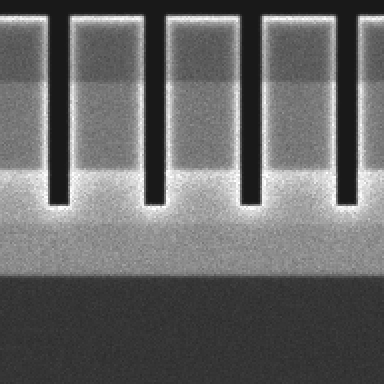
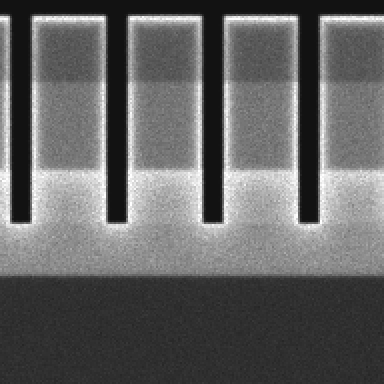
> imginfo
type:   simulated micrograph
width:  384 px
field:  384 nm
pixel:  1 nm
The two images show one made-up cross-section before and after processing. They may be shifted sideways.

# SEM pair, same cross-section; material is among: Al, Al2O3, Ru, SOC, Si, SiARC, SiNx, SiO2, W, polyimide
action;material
removed;W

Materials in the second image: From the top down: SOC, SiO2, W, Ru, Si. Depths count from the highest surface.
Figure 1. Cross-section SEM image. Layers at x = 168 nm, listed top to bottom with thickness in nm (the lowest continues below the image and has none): SOC 66, SiO2 88, W 54, Ru 52, Si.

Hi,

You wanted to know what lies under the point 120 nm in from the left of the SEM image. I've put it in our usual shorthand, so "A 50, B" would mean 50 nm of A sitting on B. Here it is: empty 208, Ru 52, Si